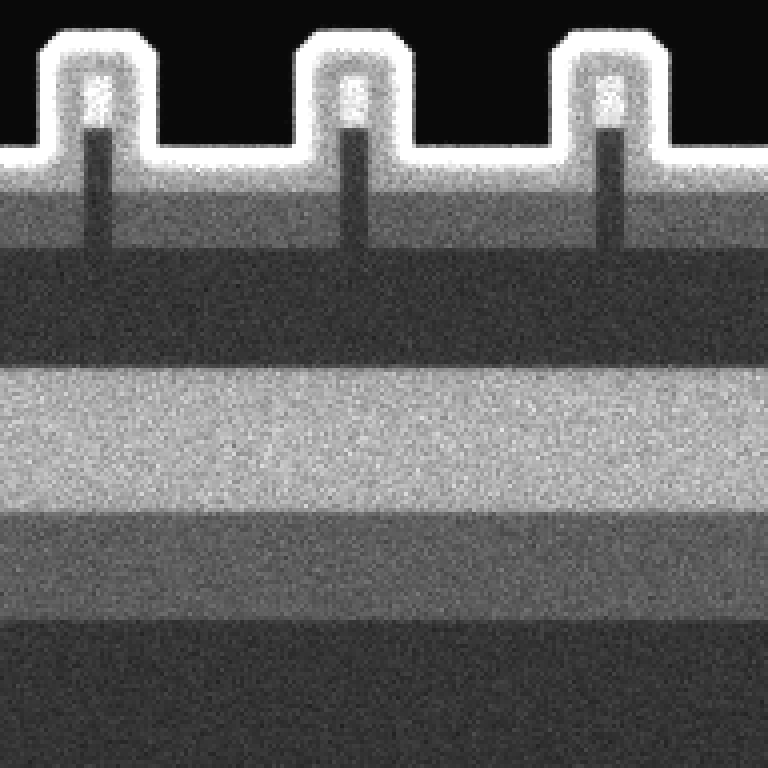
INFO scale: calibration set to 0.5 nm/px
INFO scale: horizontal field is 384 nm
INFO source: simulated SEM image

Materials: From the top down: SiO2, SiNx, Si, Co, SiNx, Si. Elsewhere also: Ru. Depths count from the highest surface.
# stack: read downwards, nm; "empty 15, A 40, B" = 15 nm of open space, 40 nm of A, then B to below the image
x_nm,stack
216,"empty 58, SiO2 22, SiNx 28, Si 60, Co 72, SiNx 54, Si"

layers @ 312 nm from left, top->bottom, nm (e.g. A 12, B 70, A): SiO2 80, SiNx 28, Si 60, Co 72, SiNx 54, Si